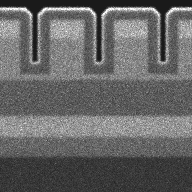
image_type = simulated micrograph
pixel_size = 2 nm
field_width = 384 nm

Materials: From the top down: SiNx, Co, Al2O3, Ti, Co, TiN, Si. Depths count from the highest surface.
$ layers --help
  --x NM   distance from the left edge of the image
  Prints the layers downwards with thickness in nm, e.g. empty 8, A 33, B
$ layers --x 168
SiNx 132, Al2O3 12, Ti 72, Co 42, TiN 40, Si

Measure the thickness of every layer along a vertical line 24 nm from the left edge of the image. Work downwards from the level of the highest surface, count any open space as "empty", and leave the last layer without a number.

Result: SiNx 24, Co 36, Al2O3 84, Ti 72, Co 42, TiN 40, Si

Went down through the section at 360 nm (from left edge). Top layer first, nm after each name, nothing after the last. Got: SiNx 24, Co 36, Al2O3 84, Ti 72, Co 42, TiN 40, Si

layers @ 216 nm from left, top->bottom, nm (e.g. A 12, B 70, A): SiNx 132, Al2O3 12, Ti 72, Co 42, TiN 40, Si